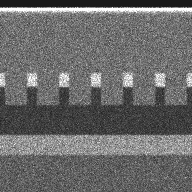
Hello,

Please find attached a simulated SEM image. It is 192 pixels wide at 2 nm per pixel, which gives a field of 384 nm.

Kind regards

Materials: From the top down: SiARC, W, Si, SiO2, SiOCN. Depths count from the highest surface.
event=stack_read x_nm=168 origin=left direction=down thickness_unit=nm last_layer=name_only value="SiARC 194, Si 60, SiO2 40, SiOCN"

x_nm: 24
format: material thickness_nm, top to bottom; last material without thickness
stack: SiARC 194, Si 60, SiO2 40, SiOCN